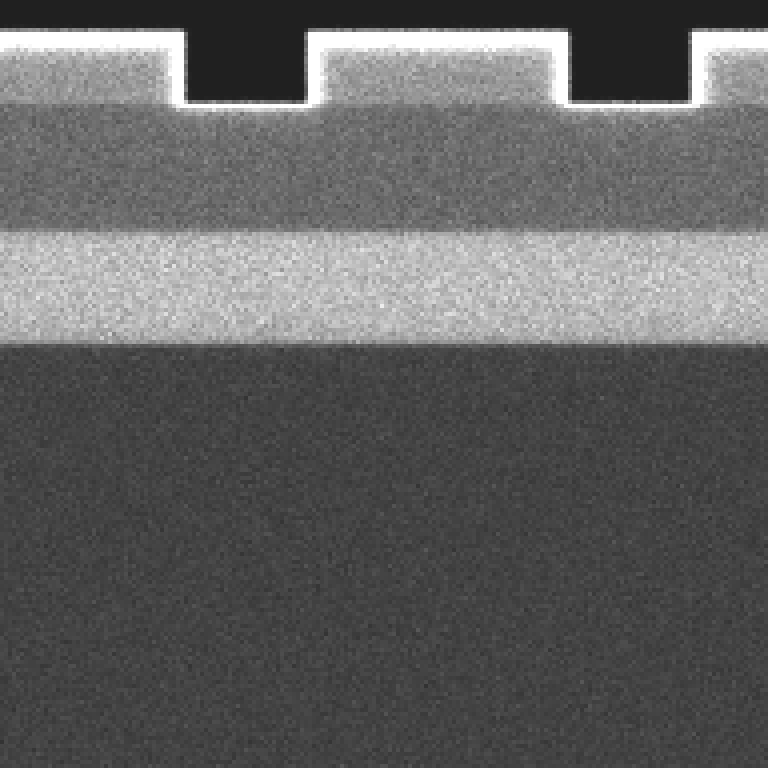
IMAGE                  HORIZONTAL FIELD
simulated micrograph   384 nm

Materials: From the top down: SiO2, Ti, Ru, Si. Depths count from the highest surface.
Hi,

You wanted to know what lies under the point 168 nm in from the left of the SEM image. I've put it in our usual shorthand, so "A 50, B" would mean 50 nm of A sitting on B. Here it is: SiO2 36, Ti 64, Ru 56, Si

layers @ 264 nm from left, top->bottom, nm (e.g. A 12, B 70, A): SiO2 36, Ti 64, Ru 56, Si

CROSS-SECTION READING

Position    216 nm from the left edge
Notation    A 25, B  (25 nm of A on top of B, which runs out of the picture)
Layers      SiO2 36, Ti 64, Ru 56, Si